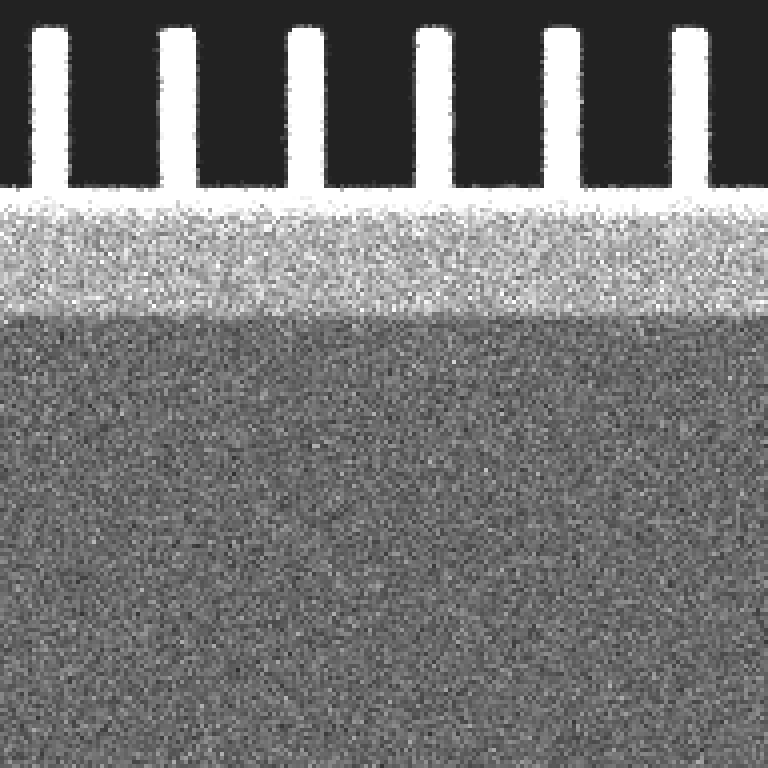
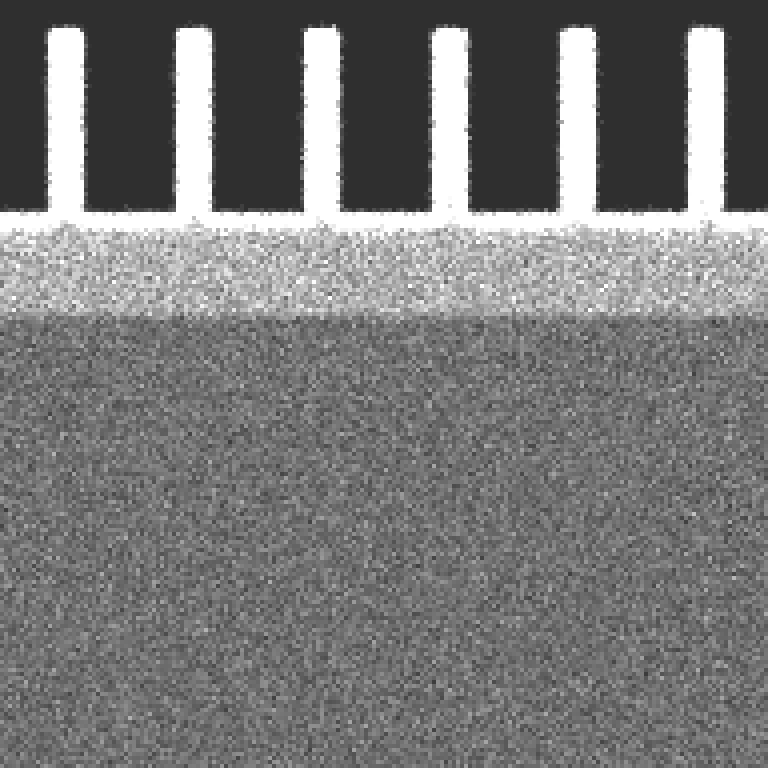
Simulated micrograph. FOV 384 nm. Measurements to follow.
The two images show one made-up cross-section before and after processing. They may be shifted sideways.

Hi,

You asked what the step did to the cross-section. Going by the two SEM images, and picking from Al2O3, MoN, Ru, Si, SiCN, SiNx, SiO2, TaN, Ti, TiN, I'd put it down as TiN, removed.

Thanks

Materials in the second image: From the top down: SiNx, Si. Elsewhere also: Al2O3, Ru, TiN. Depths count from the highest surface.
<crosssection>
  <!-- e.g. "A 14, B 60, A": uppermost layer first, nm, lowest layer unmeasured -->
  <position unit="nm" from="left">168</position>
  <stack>empty 92, SiNx 50, Si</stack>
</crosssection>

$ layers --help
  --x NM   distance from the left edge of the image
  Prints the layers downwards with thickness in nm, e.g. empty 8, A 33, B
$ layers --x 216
empty 92, SiNx 50, Si